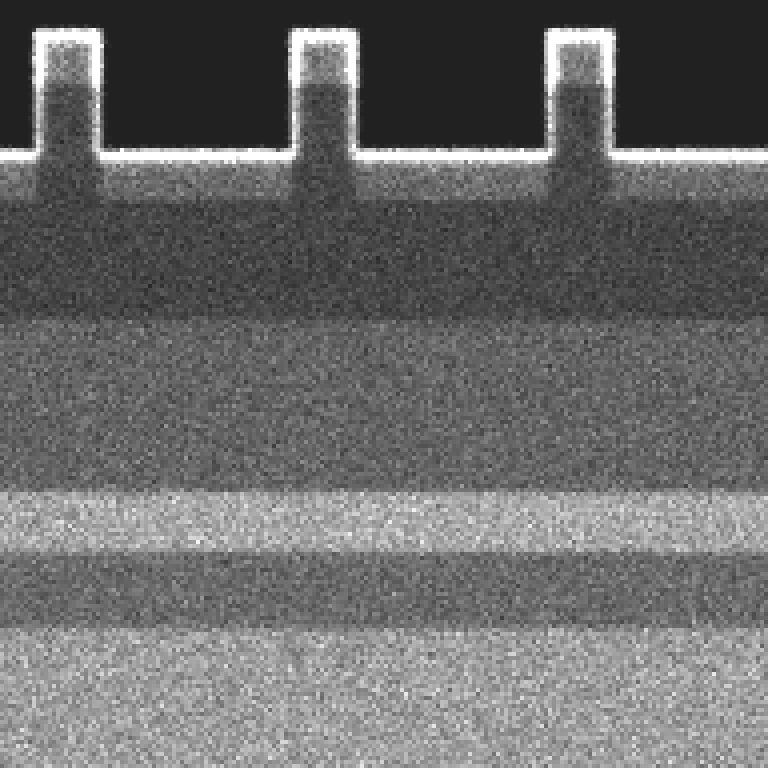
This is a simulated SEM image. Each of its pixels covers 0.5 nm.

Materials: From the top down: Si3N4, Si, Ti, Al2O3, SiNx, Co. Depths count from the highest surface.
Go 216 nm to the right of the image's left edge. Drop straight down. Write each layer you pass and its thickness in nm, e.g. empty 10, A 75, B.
empty 60, SiNx 24, Si 60, Ti 86, Al2O3 30, SiNx 38, Co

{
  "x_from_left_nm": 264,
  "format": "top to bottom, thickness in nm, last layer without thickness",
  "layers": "empty 60, SiNx 24, Si 60, Ti 86, Al2O3 30, SiNx 38, Co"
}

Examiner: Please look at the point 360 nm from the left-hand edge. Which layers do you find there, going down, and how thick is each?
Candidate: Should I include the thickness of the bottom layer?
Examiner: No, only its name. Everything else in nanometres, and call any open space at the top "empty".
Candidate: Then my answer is empty 60, SiNx 24, Si 60, Ti 86, Al2O3 30, SiNx 38, Co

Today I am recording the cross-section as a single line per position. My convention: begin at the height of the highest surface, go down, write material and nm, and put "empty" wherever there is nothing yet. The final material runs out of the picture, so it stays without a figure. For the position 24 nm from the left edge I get Si3N4 26, Si 118, Ti 86, Al2O3 30, SiNx 38, Co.